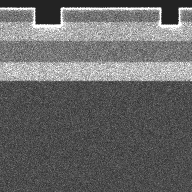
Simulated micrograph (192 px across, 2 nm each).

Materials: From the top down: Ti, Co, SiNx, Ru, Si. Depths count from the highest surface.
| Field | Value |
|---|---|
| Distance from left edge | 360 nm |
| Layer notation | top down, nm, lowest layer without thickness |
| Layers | Ti 28, Co 38, SiNx 42, Ru 38, Si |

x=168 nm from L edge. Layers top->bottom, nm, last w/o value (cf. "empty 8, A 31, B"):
Ti 28, Co 38, SiNx 42, Ru 38, Si